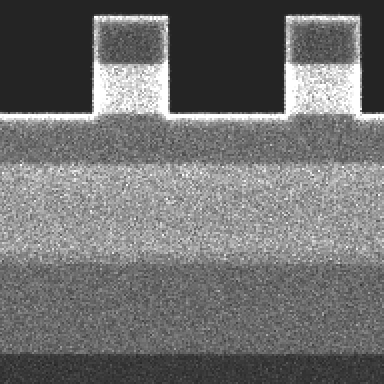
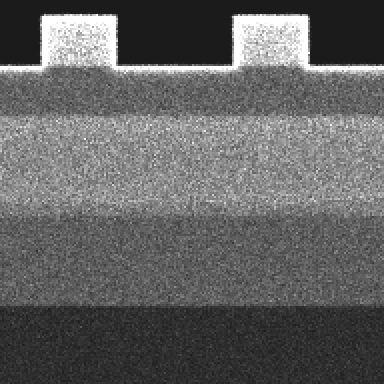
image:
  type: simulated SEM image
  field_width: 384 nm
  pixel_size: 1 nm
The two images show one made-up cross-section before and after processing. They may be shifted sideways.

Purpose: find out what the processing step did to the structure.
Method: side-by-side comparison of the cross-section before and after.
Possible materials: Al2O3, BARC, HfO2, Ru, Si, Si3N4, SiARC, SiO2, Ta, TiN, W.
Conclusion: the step removed SiARC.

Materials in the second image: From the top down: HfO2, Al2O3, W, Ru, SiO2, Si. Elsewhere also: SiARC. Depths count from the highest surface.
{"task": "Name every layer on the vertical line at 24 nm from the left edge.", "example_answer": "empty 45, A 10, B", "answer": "empty 50, Al2O3 50, W 88, Ru 12, SiO2 90, Si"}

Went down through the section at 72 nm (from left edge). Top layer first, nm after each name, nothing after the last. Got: HfO2 50, Al2O3 50, W 88, Ru 12, SiO2 90, Si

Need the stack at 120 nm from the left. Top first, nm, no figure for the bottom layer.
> empty 50, Al2O3 50, W 88, Ru 12, SiO2 90, Si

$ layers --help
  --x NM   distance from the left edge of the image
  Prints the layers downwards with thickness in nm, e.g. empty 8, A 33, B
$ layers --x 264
HfO2 50, Al2O3 50, W 88, Ru 12, SiO2 90, Si